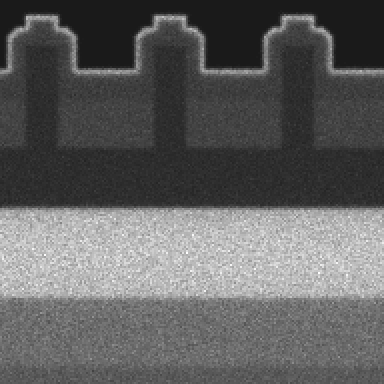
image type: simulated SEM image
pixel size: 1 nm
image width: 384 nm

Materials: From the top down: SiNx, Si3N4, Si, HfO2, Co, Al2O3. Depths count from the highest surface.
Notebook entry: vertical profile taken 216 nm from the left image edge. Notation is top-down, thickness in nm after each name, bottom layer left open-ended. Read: empty 54, SiNx 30, Si3N4 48, Si 60, HfO2 90, Co 68, Al2O3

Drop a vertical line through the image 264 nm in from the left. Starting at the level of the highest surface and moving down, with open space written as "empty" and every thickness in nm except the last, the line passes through empty 20, SiNx 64, Si3N4 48, Si 60, HfO2 90, Co 68, Al2O3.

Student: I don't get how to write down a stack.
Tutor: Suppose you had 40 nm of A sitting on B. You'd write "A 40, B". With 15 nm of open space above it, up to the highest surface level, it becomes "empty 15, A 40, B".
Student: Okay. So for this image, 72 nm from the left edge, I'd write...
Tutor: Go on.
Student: empty 18, SiNx 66, Si3N4 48, Si 60, HfO2 90, Co 68, Al2O3